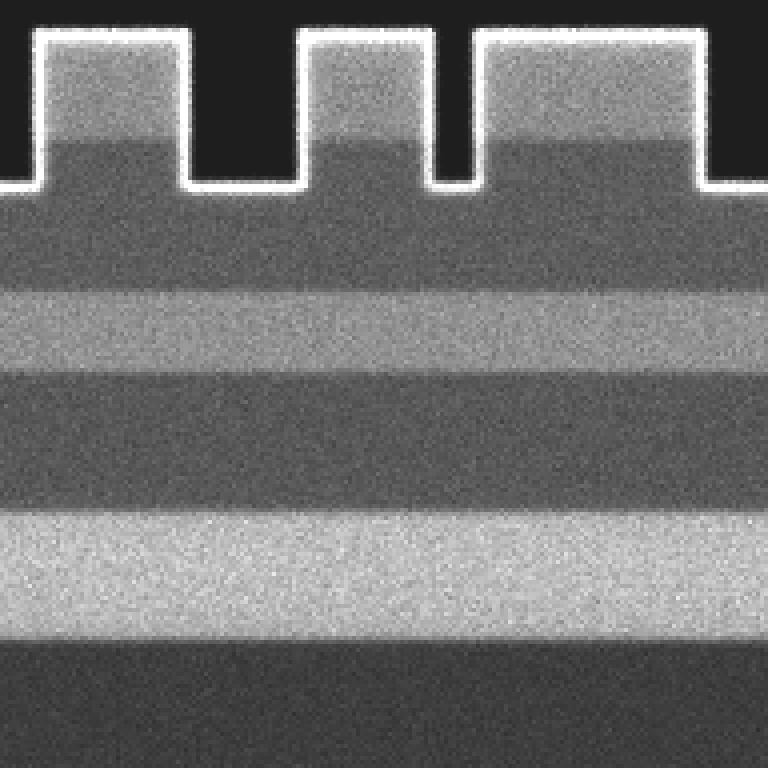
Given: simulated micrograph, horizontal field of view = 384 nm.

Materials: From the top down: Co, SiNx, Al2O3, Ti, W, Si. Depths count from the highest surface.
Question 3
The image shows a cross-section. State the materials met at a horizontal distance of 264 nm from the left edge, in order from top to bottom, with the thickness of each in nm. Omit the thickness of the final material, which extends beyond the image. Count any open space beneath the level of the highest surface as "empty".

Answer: Co 54, SiNx 76, Al2O3 40, Ti 70, W 64, Si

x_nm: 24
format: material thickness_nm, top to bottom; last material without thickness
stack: Co 54, SiNx 76, Al2O3 40, Ti 70, W 64, Si